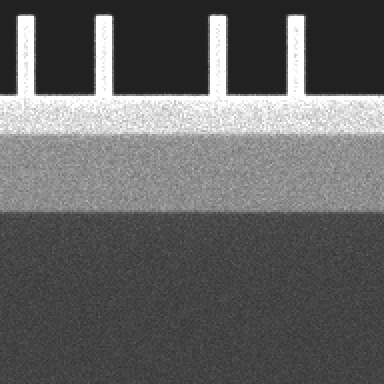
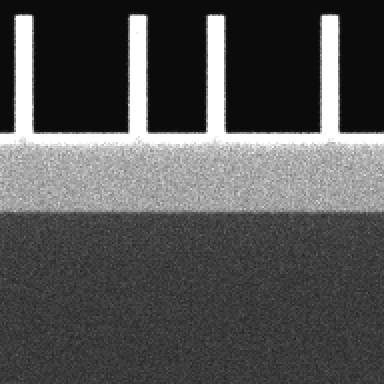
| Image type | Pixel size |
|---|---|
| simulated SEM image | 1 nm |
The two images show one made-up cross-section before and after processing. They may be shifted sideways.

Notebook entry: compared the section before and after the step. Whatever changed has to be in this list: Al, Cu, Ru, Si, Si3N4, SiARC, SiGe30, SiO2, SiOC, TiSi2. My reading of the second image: Ru removed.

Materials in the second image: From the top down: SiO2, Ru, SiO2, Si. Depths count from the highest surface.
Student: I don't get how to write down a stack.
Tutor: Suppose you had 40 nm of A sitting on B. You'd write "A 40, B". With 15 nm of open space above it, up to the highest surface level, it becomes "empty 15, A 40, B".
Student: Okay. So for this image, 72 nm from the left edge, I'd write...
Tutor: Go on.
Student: empty 118, SiO2 78, Si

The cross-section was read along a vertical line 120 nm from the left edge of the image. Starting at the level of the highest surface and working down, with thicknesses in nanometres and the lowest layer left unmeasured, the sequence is empty 118, SiO2 78, Si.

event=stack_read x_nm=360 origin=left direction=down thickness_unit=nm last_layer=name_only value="empty 118, SiO2 78, Si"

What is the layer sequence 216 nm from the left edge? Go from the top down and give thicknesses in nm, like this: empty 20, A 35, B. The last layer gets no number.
SiO2 80, Ru 38, SiO2 78, Si